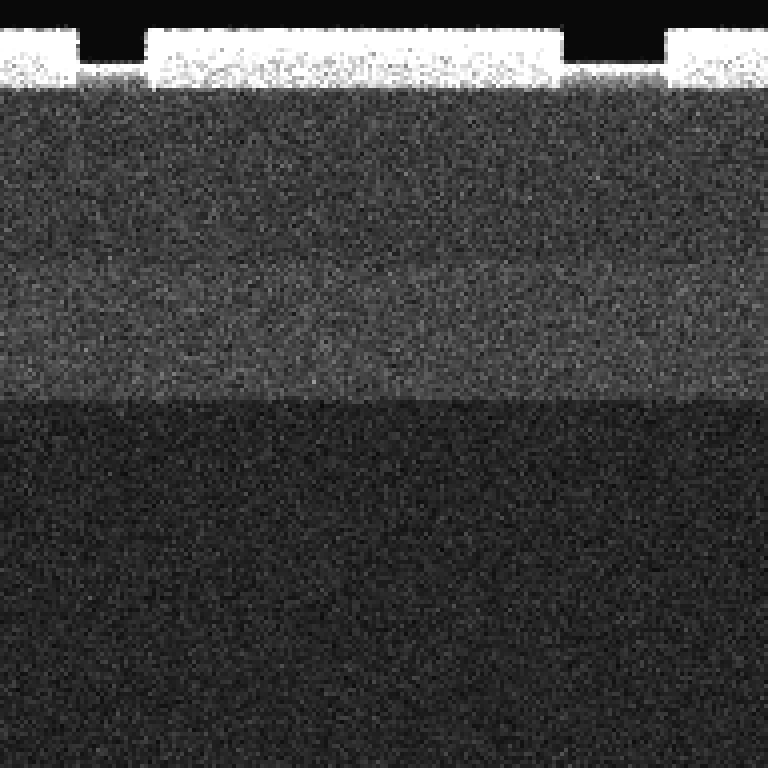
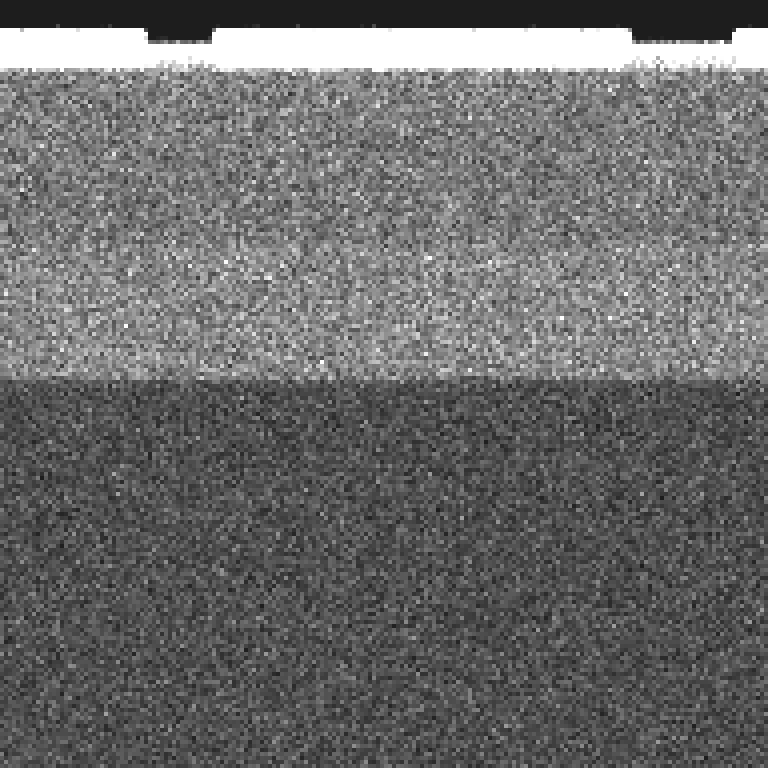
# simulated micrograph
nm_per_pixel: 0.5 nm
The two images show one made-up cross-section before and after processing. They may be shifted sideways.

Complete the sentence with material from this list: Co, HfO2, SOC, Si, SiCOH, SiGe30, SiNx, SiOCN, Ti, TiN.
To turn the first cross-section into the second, HfO2 must be removed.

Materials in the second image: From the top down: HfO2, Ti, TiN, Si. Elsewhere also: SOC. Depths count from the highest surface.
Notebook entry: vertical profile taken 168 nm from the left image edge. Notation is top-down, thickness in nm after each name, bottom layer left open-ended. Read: HfO2 18, Ti 88, TiN 68, Si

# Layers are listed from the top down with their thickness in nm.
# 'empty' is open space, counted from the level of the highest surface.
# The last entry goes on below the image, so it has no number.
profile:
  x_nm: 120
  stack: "HfO2 18, Ti 88, TiN 68, Si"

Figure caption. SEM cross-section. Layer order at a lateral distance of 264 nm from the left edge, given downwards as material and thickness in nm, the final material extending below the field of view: HfO2 18, Ti 88, TiN 68, Si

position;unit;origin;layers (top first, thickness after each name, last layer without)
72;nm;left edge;empty 6, SOC 12, Ti 88, TiN 68, Si